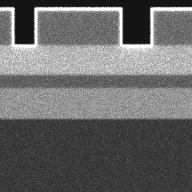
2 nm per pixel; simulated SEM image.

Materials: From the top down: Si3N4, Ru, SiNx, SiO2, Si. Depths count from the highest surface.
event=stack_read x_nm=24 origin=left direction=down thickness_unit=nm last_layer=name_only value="Si3N4 74, Ru 60, SiNx 26, SiO2 62, Si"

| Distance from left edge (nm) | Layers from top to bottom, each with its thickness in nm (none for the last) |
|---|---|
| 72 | Si3N4 74, Ru 60, SiNx 26, SiO2 62, Si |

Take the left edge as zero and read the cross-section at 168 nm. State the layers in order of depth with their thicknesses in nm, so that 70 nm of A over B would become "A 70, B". Si3N4 74, Ru 60, SiNx 26, SiO2 62, Si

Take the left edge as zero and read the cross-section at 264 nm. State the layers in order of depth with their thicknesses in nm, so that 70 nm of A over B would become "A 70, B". empty 74, Ru 60, SiNx 26, SiO2 62, Si